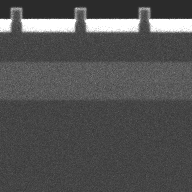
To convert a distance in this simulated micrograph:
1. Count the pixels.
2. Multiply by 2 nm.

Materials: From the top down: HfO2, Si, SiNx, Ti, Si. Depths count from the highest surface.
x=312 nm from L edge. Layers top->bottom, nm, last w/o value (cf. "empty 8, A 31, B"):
empty 24, HfO2 24, Si 60, SiNx 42, Ti 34, Si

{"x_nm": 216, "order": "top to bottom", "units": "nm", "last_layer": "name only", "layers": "empty 24, HfO2 24, Si 60, SiNx 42, Ti 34, Si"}